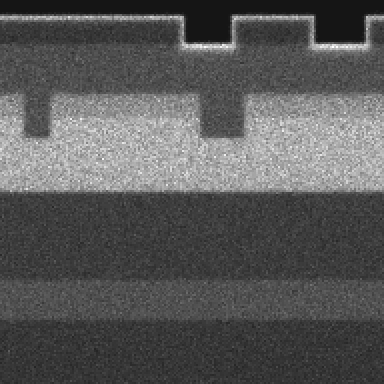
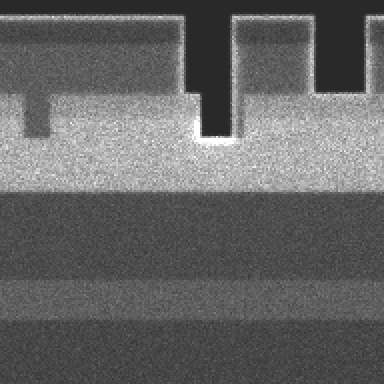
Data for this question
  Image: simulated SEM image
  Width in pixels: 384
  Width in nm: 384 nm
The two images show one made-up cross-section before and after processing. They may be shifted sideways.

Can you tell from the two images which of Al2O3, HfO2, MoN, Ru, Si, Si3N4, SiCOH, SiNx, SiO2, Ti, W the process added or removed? Yes, it removed SiO2.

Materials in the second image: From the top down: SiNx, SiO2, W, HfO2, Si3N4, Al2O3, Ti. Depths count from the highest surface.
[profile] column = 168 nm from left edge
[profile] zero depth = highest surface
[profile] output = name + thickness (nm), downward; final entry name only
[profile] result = SiNx 28, SiO2 50, W 24, HfO2 74, Si3N4 88, Al2O3 40, Ti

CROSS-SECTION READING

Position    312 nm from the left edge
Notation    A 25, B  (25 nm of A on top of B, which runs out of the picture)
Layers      SiNx 28, SiO2 50, W 24, HfO2 74, Si3N4 88, Al2O3 40, Ti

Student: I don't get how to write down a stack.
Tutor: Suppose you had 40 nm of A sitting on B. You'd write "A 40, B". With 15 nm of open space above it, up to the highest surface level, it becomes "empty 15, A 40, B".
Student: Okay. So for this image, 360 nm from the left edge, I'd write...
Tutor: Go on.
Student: empty 78, W 24, HfO2 74, Si3N4 88, Al2O3 40, Ti